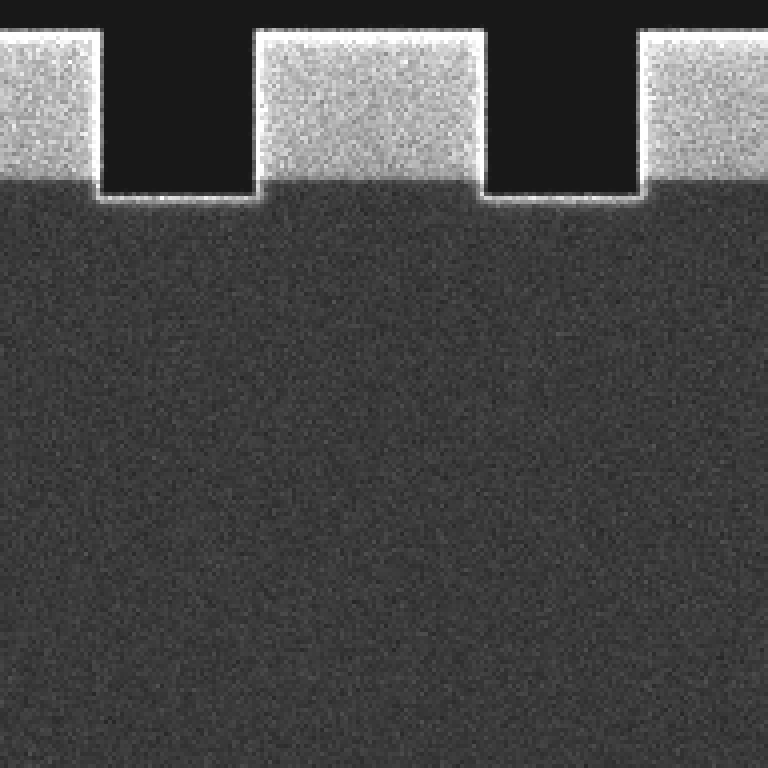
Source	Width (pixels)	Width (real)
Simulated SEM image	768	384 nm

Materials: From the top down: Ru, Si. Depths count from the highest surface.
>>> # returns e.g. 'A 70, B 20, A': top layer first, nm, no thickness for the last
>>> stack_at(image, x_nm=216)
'Ru 74, Si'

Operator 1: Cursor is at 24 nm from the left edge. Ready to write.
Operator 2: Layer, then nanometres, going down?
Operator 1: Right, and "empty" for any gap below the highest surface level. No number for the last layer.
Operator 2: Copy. Ru 74, Si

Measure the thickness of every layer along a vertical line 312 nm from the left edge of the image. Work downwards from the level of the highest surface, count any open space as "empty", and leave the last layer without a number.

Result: empty 82, Si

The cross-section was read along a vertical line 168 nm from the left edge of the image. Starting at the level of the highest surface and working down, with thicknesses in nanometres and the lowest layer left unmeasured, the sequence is Ru 74, Si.